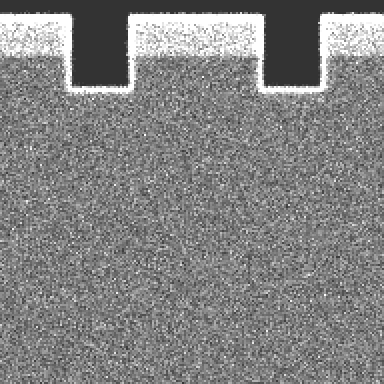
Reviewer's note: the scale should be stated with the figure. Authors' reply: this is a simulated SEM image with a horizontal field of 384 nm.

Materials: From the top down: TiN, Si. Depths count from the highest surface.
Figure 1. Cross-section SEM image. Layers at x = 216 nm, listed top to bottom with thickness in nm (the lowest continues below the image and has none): TiN 40, Si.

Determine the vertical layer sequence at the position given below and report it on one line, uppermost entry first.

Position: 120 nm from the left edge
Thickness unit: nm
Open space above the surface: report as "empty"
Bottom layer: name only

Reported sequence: empty 72, Si